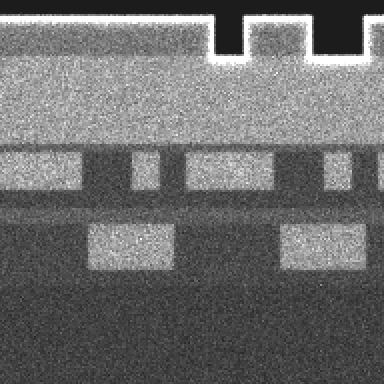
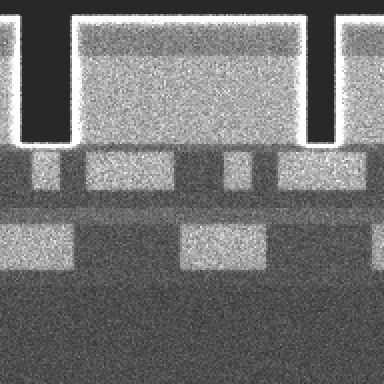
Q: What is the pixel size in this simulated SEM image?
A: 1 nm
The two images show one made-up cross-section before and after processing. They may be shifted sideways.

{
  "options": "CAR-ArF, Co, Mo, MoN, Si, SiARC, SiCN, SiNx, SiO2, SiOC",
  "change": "removed",
  "material": "SiO2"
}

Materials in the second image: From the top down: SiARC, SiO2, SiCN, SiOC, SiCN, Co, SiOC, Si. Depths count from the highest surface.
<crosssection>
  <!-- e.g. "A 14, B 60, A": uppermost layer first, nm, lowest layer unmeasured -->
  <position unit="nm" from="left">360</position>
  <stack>SiARC 40, SiO2 88, SiCN 8, Co 38, SiOC 18, SiCN 16, SiOC 62, Si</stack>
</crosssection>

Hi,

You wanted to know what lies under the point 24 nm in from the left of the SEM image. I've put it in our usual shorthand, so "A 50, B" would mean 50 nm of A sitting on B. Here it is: empty 128, SiCN 8, SiOC 56, SiCN 16, Co 46, SiOC 16, Si